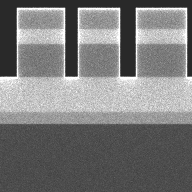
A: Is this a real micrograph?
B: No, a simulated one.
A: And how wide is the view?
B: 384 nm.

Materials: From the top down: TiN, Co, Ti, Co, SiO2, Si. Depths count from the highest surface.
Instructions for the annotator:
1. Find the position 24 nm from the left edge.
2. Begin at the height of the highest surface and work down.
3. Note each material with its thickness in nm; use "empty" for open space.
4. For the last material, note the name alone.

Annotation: empty 138, Co 70, SiO2 24, Si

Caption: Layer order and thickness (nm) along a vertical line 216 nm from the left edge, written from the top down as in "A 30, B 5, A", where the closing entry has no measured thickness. TiN 42, Co 30, Ti 66, Co 70, SiO2 24, Si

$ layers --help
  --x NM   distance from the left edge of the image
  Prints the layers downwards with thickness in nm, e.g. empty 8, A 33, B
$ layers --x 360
TiN 42, Co 30, Ti 66, Co 70, SiO2 24, Si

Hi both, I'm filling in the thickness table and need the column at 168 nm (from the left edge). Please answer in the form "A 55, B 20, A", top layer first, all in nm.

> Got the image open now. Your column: TiN 42, Co 30, Ti 66, Co 70, SiO2 24, Si